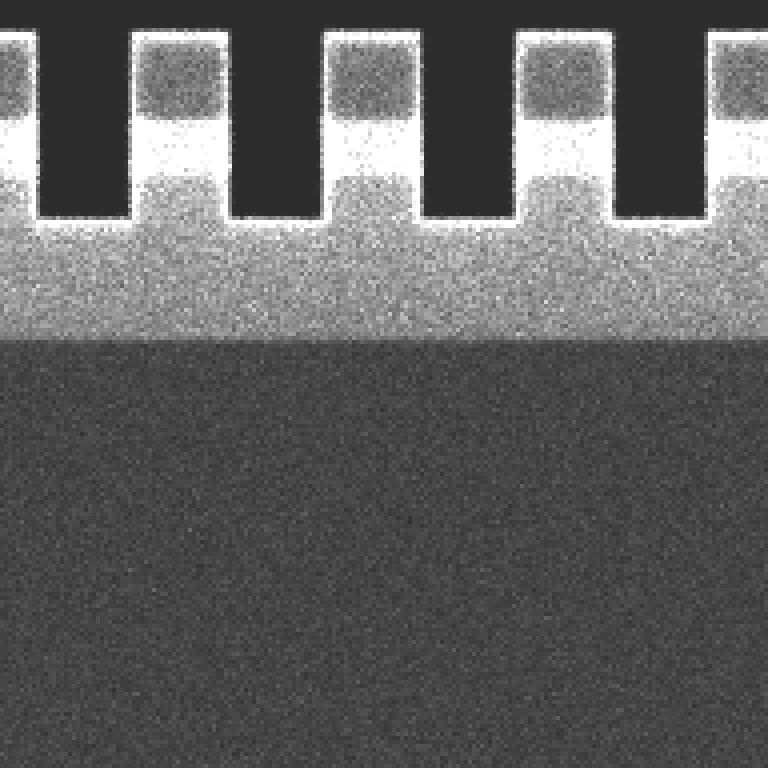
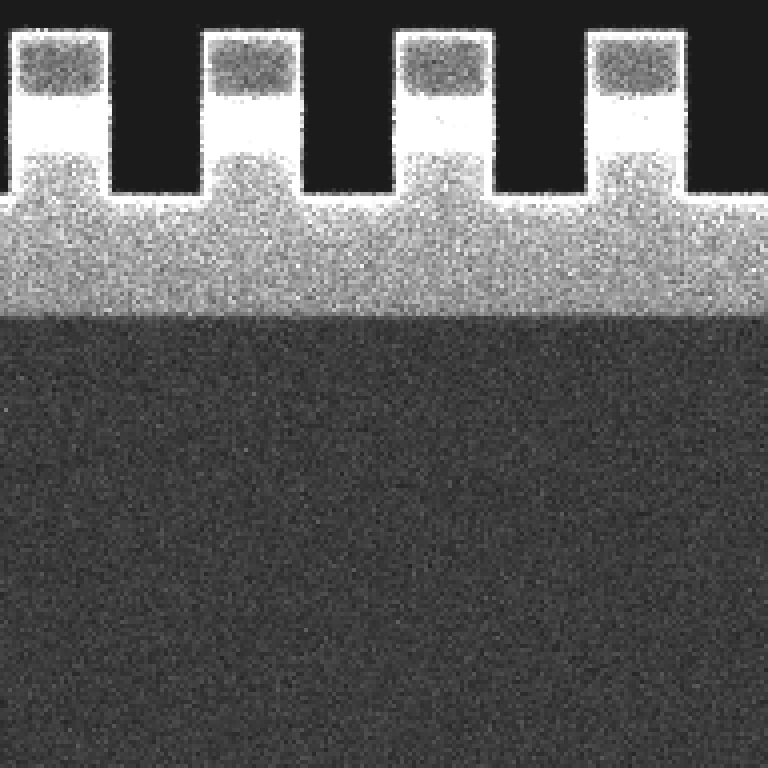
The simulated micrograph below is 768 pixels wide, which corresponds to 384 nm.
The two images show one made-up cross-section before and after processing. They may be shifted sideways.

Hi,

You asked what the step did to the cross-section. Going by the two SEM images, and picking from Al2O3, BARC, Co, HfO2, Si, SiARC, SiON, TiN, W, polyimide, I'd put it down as SiARC, removed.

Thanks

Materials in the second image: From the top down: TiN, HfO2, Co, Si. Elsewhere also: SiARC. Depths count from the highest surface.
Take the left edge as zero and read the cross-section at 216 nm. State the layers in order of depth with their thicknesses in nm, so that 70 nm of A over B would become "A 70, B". TiN 32, HfO2 28, Co 82, Si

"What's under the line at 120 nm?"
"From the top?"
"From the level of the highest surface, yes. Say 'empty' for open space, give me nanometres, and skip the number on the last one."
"TiN 32, HfO2 28, Co 82, Si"